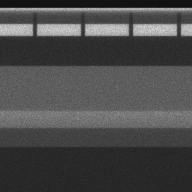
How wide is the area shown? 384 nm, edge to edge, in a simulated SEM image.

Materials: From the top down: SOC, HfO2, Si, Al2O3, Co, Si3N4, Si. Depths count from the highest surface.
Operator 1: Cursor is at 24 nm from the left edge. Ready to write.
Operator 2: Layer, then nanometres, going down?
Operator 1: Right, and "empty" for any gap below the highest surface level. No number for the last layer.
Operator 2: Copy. SOC 32, HfO2 24, Si 60, Al2O3 90, Co 34, Si3N4 38, Si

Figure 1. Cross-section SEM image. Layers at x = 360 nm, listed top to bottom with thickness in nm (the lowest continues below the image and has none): SOC 8, Si 108, Al2O3 90, Co 34, Si3N4 38, Si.